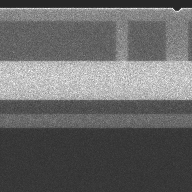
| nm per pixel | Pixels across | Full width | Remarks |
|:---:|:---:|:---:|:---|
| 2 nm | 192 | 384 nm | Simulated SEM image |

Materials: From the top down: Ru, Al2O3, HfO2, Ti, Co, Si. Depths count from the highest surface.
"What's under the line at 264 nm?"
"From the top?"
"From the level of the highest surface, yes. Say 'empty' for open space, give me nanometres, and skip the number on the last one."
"Ru 26, Al2O3 80, HfO2 78, Ti 28, Co 28, Si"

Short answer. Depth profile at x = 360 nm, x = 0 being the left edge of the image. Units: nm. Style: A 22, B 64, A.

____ empty 2, Ru 104, HfO2 78, Ti 28, Co 28, Si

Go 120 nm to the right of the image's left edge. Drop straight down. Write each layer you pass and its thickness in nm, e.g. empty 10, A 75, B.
Ru 26, Al2O3 80, HfO2 78, Ti 28, Co 28, Si